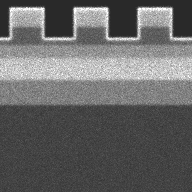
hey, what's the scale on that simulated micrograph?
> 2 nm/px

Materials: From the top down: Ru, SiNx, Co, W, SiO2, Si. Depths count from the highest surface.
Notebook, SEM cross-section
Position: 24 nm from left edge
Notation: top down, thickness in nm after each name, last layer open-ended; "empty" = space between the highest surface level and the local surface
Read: Ru 38, SiNx 36, Co 26, W 44, SiO2 50, Si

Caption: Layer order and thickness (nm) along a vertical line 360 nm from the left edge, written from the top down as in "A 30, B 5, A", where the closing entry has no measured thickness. empty 60, SiNx 14, Co 26, W 44, SiO2 50, Si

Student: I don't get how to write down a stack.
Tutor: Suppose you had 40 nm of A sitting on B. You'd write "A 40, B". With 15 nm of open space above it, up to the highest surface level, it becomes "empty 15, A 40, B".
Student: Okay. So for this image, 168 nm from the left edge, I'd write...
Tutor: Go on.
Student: Ru 38, SiNx 36, Co 26, W 44, SiO2 50, Si